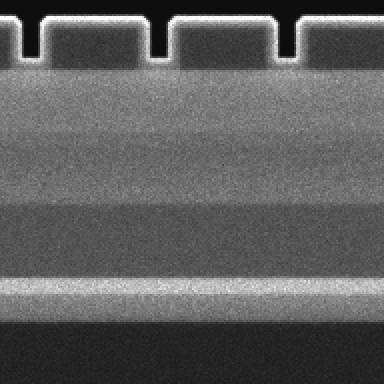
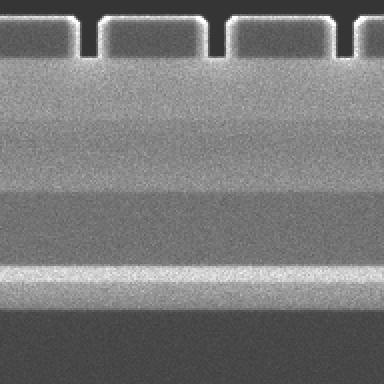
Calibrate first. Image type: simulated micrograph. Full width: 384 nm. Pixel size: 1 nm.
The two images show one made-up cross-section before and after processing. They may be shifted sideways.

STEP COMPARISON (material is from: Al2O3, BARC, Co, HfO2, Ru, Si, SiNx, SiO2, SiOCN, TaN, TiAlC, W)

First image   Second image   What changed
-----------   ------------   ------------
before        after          Al2O3, removed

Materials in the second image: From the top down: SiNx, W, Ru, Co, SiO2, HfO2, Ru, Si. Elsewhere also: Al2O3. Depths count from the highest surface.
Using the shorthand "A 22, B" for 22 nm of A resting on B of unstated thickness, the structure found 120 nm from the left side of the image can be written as SiNx 42, W 62, Ru 14, Co 58, SiO2 74, HfO2 16, Ru 28, Si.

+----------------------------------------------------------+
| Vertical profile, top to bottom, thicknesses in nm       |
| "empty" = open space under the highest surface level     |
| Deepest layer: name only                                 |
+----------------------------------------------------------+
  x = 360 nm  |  Al2O3 42, W 62, Ru 14, Co 58, SiO2 74, HfO2 16, Ru 28, Si